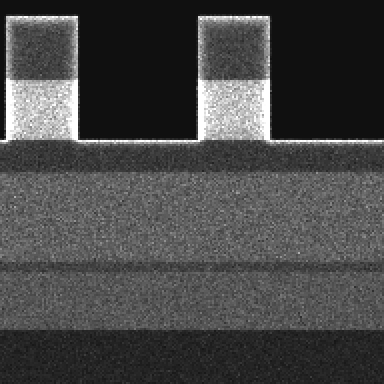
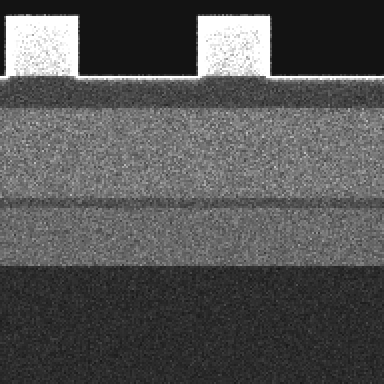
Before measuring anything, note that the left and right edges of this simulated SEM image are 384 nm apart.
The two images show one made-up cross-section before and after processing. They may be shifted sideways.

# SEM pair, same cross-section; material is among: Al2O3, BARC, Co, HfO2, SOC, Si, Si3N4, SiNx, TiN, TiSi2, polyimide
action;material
removed;SOC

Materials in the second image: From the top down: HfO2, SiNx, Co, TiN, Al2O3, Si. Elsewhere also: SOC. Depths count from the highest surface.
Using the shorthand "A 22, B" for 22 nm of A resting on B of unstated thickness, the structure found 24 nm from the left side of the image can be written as HfO2 60, SiNx 32, Co 90, TiN 10, Al2O3 58, Si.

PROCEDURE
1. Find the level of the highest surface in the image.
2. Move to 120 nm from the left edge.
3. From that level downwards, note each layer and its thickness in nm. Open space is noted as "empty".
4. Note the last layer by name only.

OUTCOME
empty 60, SiNx 32, Co 90, TiN 10, Al2O3 58, Si